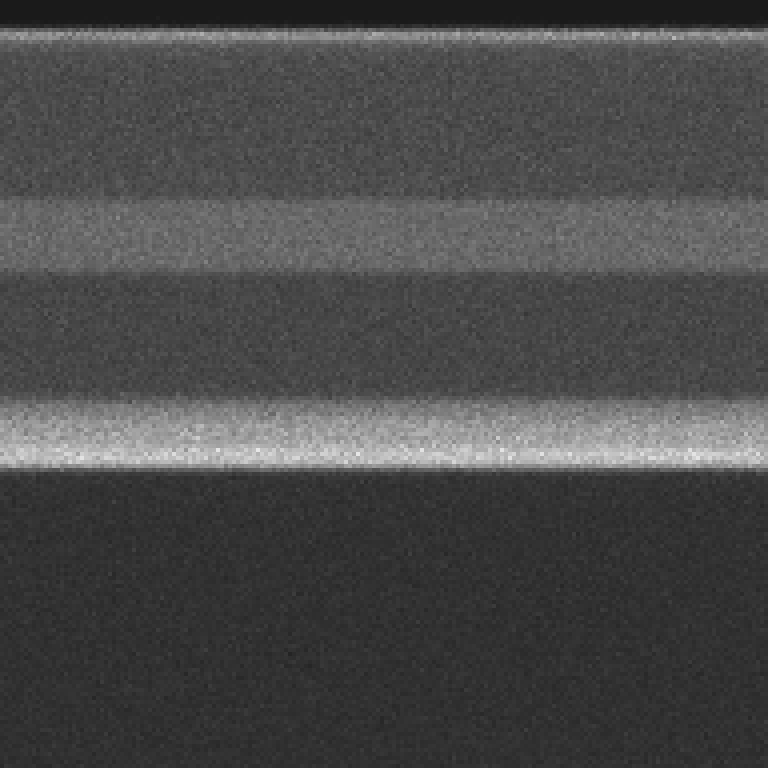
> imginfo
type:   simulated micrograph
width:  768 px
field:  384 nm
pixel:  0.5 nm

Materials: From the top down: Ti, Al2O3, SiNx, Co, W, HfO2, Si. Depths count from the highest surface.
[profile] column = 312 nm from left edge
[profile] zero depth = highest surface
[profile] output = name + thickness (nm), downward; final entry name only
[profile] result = Ti 84, Al2O3 36, SiNx 64, Co 10, W 14, HfO2 10, Si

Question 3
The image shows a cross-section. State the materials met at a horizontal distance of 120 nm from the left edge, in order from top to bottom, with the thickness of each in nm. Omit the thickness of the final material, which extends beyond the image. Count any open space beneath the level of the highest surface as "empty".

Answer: Ti 84, Al2O3 36, SiNx 64, Co 10, W 14, HfO2 10, Si